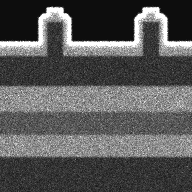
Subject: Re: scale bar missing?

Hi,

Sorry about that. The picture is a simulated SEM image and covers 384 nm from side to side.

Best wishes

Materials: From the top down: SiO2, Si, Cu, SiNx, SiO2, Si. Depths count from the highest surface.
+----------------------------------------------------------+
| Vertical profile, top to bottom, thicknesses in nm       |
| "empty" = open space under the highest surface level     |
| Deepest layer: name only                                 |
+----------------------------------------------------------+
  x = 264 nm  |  empty 68, SiO2 28, Si 60, Cu 52, SiNx 46, SiO2 44, Si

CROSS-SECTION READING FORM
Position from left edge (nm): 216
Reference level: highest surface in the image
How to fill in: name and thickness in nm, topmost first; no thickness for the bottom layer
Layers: empty 68, SiO2 28, Si 60, Cu 52, SiNx 46, SiO2 44, Si